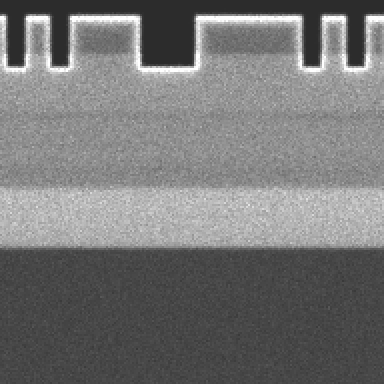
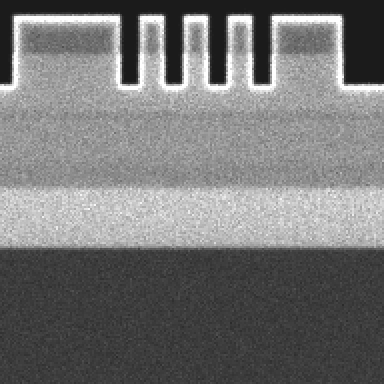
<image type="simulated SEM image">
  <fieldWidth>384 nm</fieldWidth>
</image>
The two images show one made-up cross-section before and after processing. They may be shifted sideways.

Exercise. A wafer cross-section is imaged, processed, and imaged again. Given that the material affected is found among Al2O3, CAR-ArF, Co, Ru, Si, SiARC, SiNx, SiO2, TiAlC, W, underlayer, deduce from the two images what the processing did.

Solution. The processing removed Ru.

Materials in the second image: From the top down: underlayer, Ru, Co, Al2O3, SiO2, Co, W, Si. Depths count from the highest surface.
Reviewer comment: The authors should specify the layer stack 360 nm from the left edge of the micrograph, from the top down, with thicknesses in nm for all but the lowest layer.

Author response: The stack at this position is empty 70, Ru 26, Co 8, Al2O3 38, SiO2 8, Co 22, W 60, Si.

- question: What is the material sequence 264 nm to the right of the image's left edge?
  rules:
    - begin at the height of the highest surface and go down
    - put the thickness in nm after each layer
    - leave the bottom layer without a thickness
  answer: empty 70, Ru 26, Co 8, Al2O3 38, SiO2 8, Co 22, W 60, Si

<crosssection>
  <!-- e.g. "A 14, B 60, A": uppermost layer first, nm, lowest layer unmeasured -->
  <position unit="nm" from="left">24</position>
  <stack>underlayer 38, Ru 58, Co 8, Al2O3 38, SiO2 8, Co 22, W 60, Si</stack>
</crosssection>